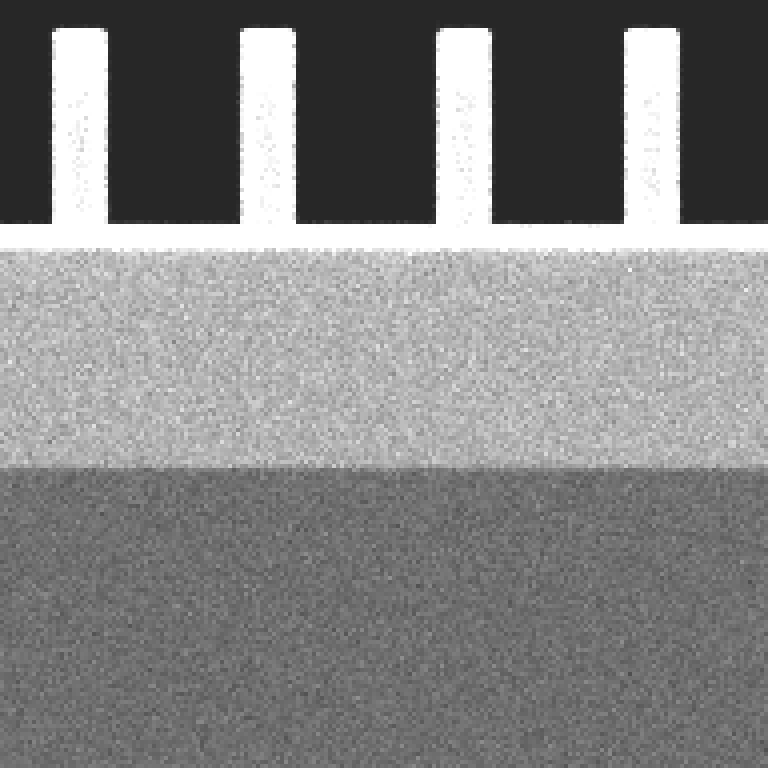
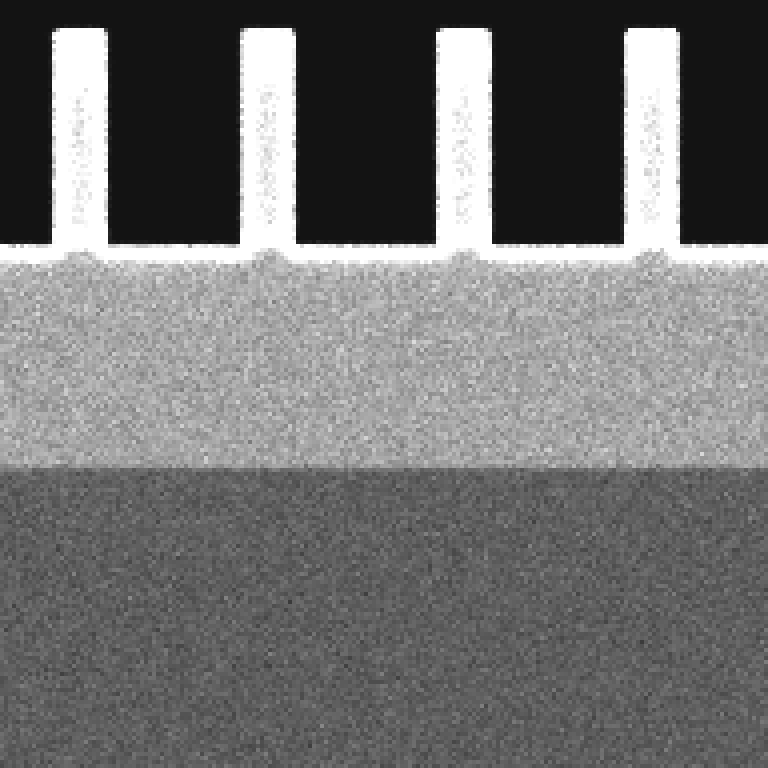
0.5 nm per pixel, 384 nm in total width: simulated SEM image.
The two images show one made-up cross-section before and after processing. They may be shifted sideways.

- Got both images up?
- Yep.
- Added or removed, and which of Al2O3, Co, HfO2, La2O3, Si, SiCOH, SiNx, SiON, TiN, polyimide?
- removed, Co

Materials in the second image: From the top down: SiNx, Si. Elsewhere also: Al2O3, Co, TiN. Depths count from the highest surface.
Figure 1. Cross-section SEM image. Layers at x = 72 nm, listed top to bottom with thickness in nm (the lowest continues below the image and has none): empty 108, SiNx 110, Si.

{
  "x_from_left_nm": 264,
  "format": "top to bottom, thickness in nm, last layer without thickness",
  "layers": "empty 108, SiNx 110, Si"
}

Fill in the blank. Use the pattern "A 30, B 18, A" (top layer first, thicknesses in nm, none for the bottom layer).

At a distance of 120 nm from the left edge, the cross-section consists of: empty 108, SiNx 110, Si